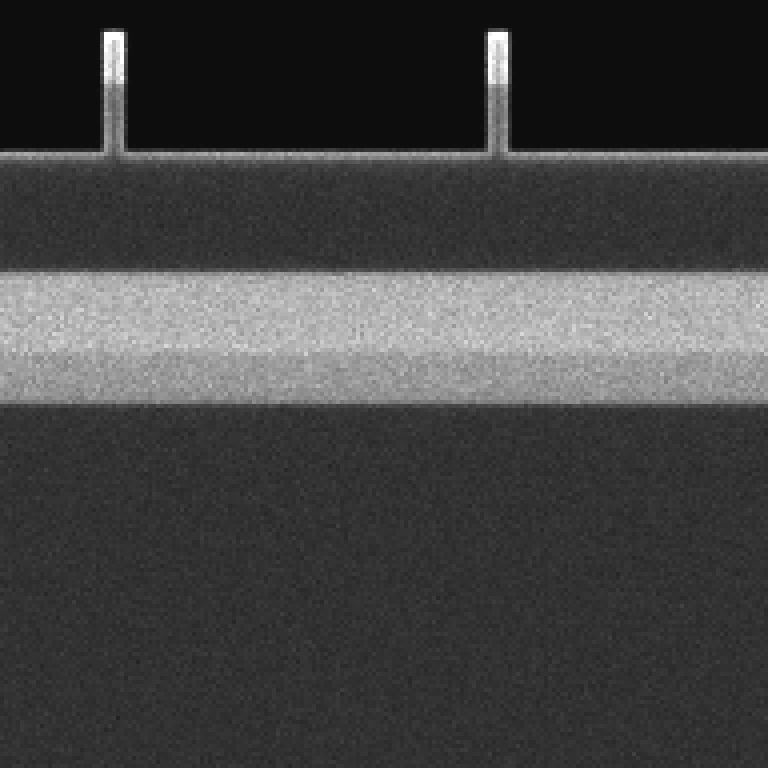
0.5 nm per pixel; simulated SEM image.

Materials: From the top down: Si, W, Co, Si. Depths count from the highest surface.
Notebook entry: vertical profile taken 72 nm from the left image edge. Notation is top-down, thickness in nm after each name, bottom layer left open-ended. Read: empty 60, Si 60, W 40, Co 26, Si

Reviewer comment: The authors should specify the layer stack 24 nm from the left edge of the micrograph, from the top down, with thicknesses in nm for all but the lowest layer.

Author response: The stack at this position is empty 60, Si 60, W 40, Co 26, Si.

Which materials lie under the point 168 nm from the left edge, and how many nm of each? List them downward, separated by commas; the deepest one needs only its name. empty 60, Si 60, W 40, Co 26, Si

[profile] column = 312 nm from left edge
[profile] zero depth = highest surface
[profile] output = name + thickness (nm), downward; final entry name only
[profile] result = empty 60, Si 60, W 40, Co 26, Si